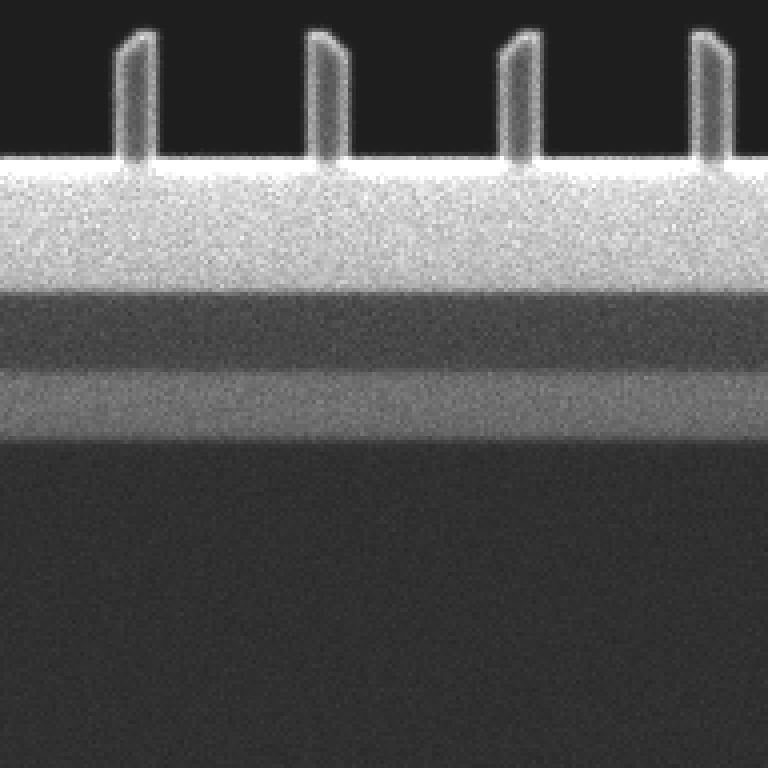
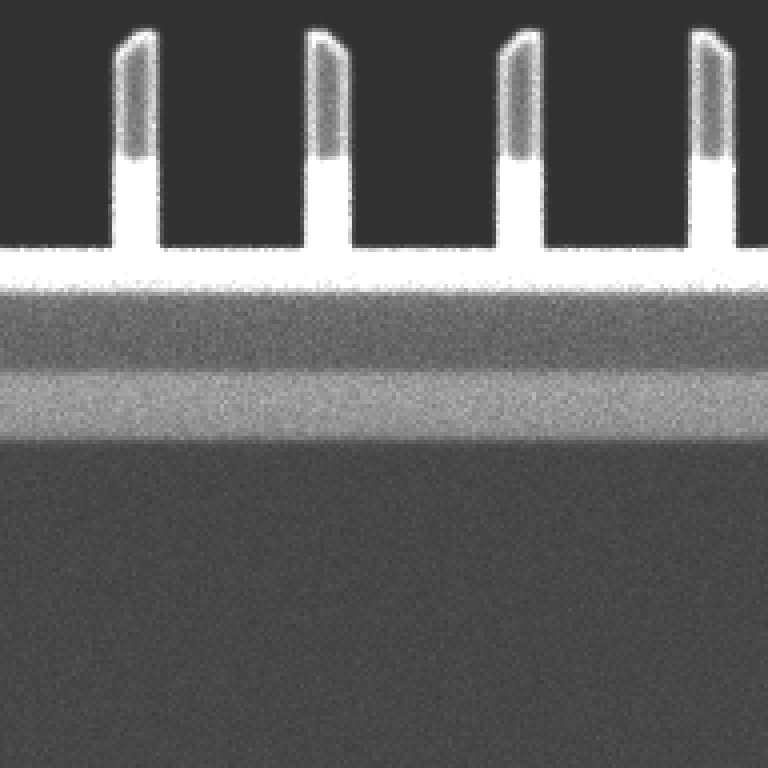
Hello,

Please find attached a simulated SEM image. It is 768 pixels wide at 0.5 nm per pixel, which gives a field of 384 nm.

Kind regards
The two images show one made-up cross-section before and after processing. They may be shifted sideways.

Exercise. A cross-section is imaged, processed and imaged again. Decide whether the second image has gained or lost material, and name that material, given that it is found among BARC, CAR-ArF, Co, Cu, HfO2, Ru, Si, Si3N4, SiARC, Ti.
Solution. removed: HfO2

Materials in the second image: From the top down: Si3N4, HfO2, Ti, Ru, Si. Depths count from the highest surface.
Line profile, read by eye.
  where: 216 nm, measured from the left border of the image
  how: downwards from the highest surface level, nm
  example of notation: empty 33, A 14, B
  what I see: empty 110, HfO2 20, Ti 40, Ru 34, Si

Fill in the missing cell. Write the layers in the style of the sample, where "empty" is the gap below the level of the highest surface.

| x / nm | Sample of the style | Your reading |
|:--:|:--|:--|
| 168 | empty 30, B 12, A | empty 6, Si3N4 58, HfO2 66, Ti 40, Ru 34, Si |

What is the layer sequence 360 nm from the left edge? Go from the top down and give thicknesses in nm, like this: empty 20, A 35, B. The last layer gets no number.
empty 6, Si3N4 58, HfO2 66, Ti 40, Ru 34, Si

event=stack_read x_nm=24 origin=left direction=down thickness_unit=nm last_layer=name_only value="empty 110, HfO2 20, Ti 40, Ru 34, Si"